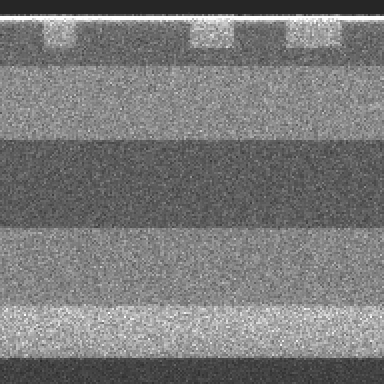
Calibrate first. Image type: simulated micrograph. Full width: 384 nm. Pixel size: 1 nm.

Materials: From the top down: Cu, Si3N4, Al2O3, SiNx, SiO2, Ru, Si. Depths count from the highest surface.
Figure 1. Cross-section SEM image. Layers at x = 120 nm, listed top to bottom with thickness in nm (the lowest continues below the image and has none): Si3N4 50, Al2O3 74, SiNx 88, SiO2 78, Ru 52, Si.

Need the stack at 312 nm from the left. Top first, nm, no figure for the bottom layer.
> Cu 32, Si3N4 18, Al2O3 74, SiNx 88, SiO2 78, Ru 52, Si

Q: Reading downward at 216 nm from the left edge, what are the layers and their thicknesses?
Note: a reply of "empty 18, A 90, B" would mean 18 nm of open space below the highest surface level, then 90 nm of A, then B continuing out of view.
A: Cu 32, Si3N4 18, Al2O3 74, SiNx 88, SiO2 78, Ru 52, Si